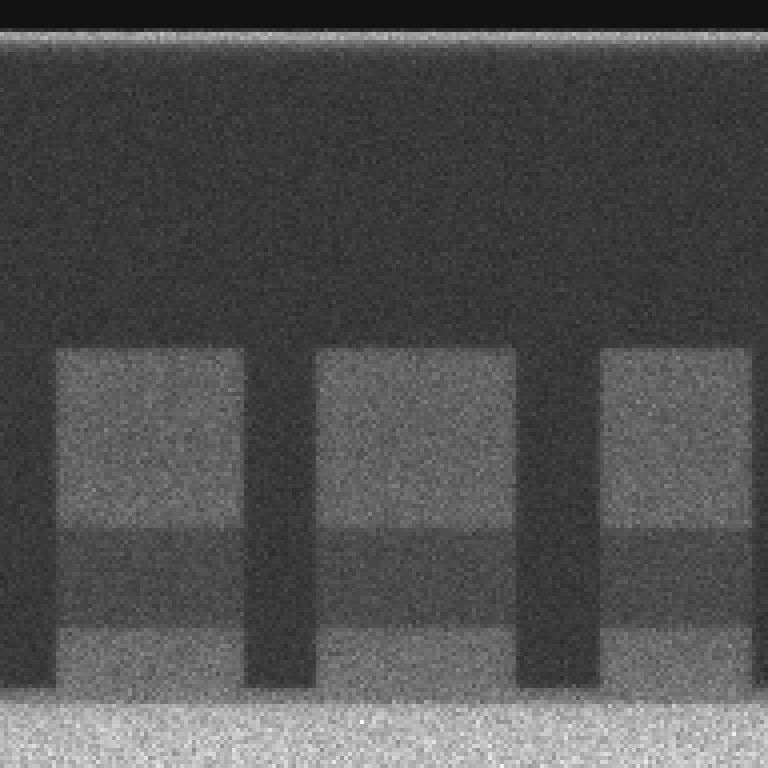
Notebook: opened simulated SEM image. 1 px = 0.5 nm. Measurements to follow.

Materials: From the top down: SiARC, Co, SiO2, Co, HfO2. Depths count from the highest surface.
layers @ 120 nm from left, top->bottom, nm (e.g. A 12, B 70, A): SiARC 158, Co 90, SiO2 50, Co 38, HfO2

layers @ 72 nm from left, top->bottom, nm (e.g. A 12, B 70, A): SiARC 158, Co 90, SiO2 50, Co 38, HfO2